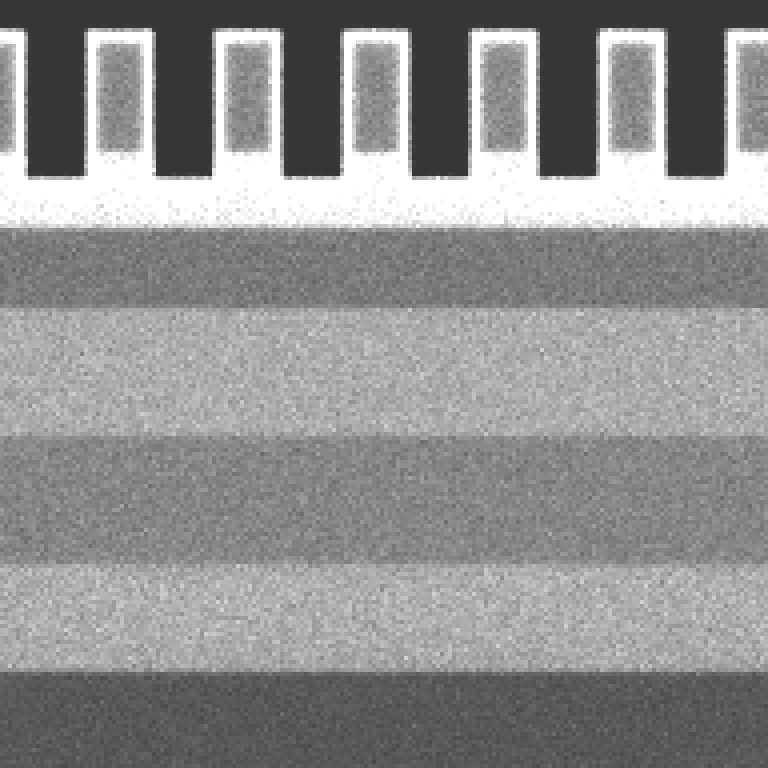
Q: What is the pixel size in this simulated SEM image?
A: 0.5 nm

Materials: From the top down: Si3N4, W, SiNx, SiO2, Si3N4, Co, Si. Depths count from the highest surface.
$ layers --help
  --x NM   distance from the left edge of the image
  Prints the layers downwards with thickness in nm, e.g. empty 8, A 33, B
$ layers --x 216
empty 74, W 24, SiNx 40, SiO2 64, Si3N4 64, Co 54, Si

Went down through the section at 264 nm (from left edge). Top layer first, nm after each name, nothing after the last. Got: Si3N4 60, W 38, SiNx 40, SiO2 64, Si3N4 64, Co 54, Si